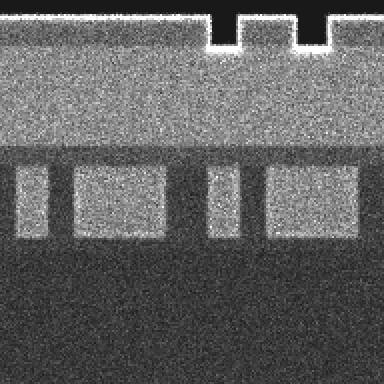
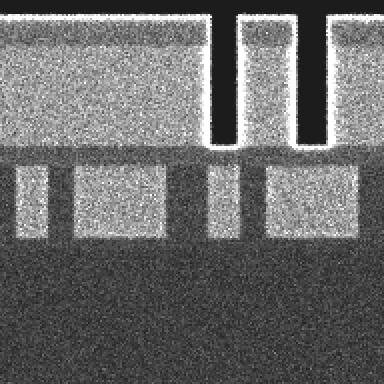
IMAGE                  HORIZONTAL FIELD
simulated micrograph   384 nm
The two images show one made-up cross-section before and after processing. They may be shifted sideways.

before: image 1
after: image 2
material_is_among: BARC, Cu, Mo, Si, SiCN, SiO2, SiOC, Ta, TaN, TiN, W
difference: SiO2, removed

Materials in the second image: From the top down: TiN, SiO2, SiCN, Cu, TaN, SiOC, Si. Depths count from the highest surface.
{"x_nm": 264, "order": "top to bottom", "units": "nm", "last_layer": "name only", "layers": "TiN 30, SiO2 100, SiCN 20, SiOC 84, Si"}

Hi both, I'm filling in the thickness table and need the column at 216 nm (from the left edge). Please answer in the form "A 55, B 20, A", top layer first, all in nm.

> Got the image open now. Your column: empty 130, SiCN 20, Cu 66, TaN 6, SiOC 12, Si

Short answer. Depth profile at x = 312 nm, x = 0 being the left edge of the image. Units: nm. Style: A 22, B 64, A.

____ empty 130, SiCN 20, Cu 66, TaN 6, SiOC 12, Si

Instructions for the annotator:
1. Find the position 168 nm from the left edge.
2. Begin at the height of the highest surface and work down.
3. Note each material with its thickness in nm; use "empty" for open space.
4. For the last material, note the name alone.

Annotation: TiN 30, SiO2 100, SiCN 20, SiOC 84, Si